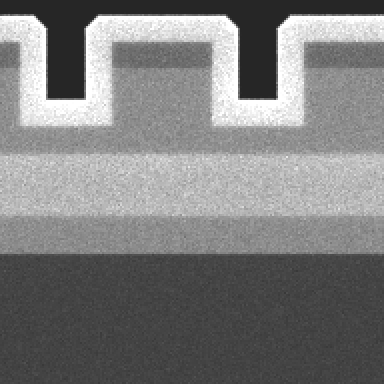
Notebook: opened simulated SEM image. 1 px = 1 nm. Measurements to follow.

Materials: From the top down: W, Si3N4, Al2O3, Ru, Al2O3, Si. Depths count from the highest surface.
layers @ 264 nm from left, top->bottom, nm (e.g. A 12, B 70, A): empty 84, W 26, Al2O3 28, Ru 62, Al2O3 38, Si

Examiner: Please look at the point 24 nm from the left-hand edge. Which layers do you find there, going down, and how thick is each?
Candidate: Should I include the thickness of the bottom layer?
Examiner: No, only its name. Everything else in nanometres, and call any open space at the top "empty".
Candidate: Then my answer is W 110, Al2O3 28, Ru 62, Al2O3 38, Si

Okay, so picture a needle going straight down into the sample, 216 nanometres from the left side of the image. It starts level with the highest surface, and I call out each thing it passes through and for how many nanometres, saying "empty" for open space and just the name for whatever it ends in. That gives W 110, Al2O3 28, Ru 62, Al2O3 38, Si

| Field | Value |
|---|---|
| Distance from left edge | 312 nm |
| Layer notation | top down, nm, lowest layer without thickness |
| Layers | W 26, Si3N4 26, Al2O3 86, Ru 62, Al2O3 38, Si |